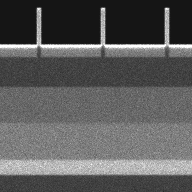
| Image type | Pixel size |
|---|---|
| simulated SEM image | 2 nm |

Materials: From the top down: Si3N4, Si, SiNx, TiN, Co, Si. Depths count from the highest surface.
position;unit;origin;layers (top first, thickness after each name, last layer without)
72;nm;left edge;empty 74, Si3N4 24, Si 60, SiNx 72, TiN 74, Co 30, Si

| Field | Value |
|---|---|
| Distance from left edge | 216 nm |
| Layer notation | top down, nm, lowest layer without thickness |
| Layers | empty 74, Si3N4 24, Si 60, SiNx 72, TiN 74, Co 30, Si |